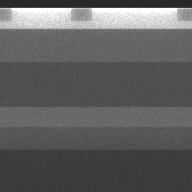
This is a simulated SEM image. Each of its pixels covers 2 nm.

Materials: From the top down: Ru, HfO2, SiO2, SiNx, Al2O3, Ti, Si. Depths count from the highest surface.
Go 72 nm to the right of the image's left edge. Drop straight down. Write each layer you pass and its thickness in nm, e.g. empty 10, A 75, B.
HfO2 42, SiO2 66, SiNx 90, Al2O3 40, Ti 46, Si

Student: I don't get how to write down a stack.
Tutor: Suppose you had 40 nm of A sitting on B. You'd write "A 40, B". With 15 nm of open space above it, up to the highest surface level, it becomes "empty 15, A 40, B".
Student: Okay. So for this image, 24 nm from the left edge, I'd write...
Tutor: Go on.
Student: HfO2 42, SiO2 66, SiNx 90, Al2O3 40, Ti 46, Si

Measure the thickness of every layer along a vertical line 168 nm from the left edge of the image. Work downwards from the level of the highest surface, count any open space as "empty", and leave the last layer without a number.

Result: Ru 26, HfO2 16, SiO2 66, SiNx 90, Al2O3 40, Ti 46, Si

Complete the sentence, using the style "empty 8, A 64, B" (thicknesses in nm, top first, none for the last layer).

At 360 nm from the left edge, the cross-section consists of Ru 26, HfO2 16, SiO2 66, SiNx 90, Al2O3 40, Ti 46, Si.